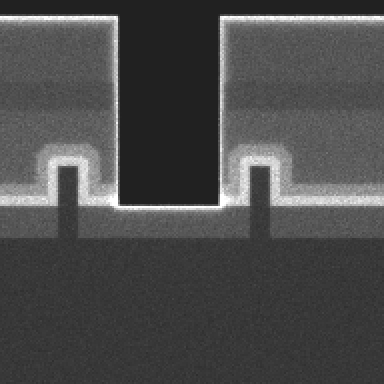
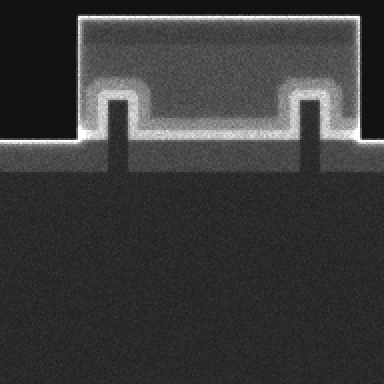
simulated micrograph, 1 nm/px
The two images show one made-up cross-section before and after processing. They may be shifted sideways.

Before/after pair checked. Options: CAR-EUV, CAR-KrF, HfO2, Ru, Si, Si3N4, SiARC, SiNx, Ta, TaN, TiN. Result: removed SiARC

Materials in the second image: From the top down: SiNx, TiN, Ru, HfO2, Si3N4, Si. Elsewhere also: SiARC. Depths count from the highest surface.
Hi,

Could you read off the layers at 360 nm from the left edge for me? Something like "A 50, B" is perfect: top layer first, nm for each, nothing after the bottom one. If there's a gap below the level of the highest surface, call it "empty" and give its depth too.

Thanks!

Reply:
empty 124, Si3N4 32, Si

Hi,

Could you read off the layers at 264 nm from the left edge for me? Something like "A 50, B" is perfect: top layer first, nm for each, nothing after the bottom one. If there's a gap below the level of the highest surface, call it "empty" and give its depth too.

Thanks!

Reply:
SiNx 28, TiN 74, Ru 12, HfO2 10, Si3N4 32, Si